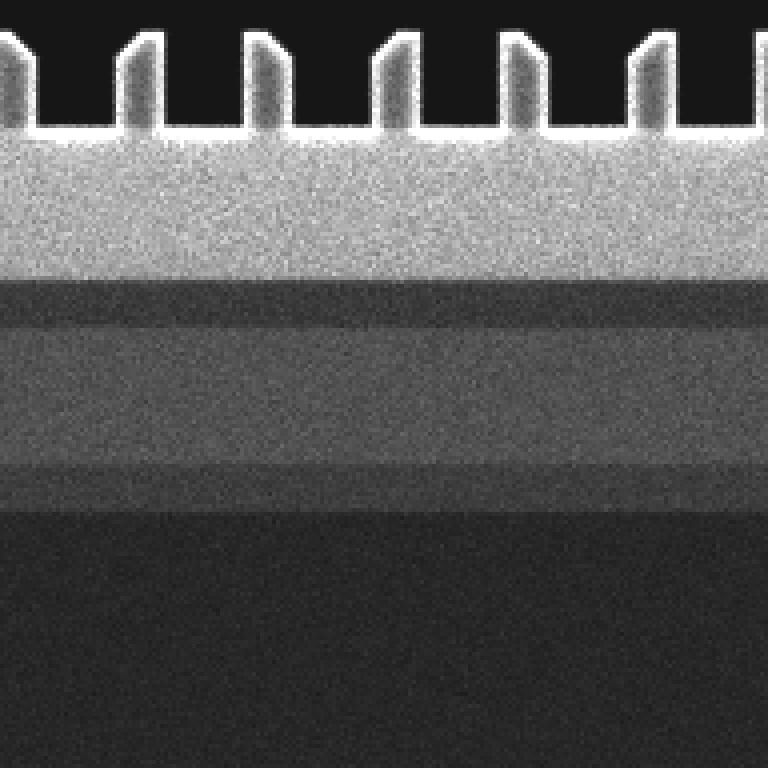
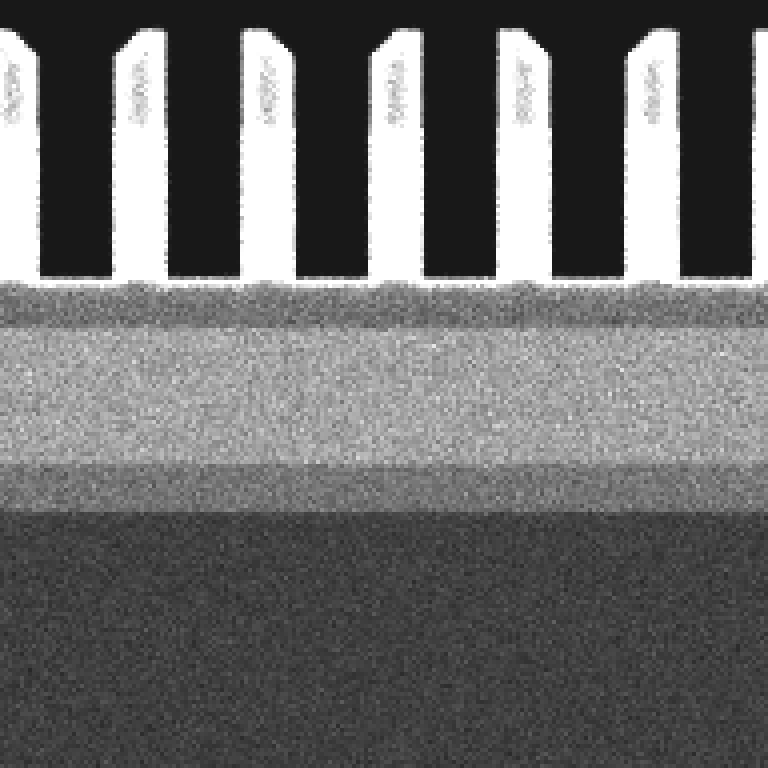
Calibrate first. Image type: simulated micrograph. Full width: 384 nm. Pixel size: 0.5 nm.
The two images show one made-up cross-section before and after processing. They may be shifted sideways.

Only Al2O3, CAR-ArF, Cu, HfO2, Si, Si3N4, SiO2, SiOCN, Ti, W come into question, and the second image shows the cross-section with HfO2 removed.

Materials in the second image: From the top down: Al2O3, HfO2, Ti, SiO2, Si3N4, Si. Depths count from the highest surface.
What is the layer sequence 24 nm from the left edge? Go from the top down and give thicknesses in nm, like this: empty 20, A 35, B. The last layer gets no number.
empty 124, Ti 24, SiO2 68, Si3N4 24, Si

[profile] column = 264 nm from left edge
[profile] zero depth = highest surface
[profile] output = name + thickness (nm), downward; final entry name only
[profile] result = empty 4, Al2O3 44, HfO2 76, Ti 24, SiO2 68, Si3N4 24, Si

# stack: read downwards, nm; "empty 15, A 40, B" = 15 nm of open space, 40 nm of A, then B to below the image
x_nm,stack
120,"empty 124, Ti 24, SiO2 68, Si3N4 24, Si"